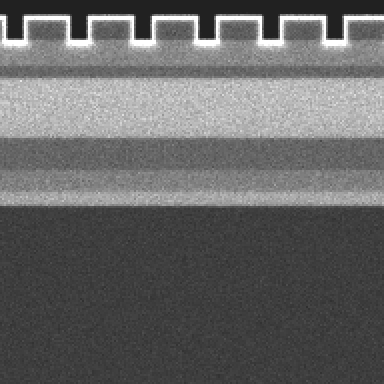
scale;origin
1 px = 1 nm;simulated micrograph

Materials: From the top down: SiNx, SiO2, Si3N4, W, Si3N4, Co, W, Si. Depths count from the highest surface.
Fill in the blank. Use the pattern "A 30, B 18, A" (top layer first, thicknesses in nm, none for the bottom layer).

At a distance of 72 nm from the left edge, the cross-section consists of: empty 24, SiO2 26, Si3N4 12, W 60, Si3N4 32, Co 22, W 14, Si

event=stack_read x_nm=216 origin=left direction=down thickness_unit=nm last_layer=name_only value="SiNx 24, SiO2 26, Si3N4 12, W 60, Si3N4 32, Co 22, W 14, Si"